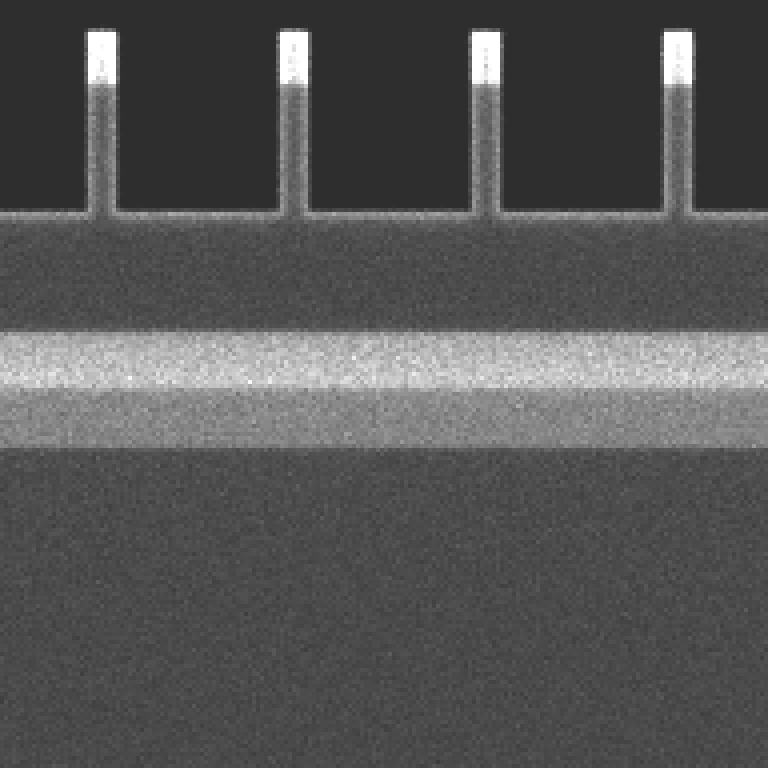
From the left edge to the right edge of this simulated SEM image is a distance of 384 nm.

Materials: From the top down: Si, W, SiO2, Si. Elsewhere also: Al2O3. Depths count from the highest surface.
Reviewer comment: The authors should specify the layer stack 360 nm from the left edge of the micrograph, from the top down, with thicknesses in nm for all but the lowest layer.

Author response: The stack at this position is empty 90, Si 60, W 28, SiO2 30, Si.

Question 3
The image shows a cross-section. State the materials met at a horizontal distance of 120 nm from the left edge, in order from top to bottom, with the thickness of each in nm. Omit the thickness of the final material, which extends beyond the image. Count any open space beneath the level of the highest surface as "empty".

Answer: empty 90, Si 60, W 28, SiO2 30, Si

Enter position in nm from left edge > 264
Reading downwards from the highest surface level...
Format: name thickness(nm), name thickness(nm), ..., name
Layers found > empty 90, Si 60, W 28, SiO2 30, Si